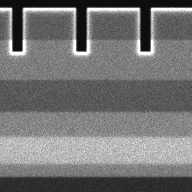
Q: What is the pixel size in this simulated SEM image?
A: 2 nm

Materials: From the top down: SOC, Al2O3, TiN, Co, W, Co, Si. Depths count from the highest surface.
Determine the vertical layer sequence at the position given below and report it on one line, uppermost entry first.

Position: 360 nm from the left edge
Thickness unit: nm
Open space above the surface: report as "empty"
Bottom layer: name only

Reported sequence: SOC 64, Al2O3 80, TiN 64, Co 50, W 54, Co 26, Si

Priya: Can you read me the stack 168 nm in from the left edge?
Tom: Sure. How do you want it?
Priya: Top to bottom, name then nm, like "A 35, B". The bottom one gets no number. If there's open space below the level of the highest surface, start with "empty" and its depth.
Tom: empty 88, Al2O3 56, TiN 64, Co 50, W 54, Co 26, Si